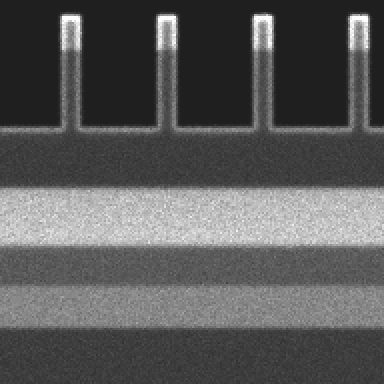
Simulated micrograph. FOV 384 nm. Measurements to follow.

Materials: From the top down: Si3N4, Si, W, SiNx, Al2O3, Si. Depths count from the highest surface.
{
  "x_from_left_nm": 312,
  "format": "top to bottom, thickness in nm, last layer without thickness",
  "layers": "empty 112, Si 60, W 58, SiNx 40, Al2O3 42, Si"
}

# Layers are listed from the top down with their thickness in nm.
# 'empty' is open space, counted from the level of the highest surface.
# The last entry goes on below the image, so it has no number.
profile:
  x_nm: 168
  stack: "Si3N4 34, Si 138, W 58, SiNx 40, Al2O3 42, Si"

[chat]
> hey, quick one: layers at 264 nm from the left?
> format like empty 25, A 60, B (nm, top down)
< Si3N4 34, Si 138, W 58, SiNx 40, Al2O3 42, Si